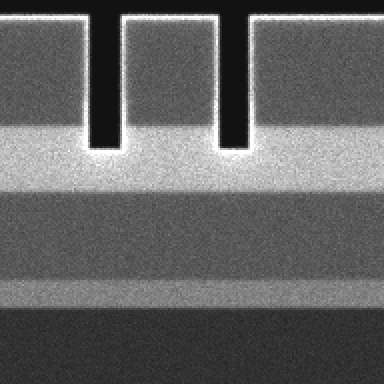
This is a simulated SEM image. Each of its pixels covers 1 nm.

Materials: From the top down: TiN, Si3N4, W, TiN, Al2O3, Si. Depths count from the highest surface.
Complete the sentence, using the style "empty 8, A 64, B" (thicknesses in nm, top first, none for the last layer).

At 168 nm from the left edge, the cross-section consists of TiN 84, Si3N4 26, W 66, TiN 88, Al2O3 28, Si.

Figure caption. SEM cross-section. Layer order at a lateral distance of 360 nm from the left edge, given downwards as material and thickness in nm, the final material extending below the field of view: TiN 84, Si3N4 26, W 66, TiN 88, Al2O3 28, Si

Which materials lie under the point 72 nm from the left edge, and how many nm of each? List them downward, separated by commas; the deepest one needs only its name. TiN 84, Si3N4 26, W 66, TiN 88, Al2O3 28, Si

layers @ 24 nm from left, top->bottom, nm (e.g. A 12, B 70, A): TiN 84, Si3N4 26, W 66, TiN 88, Al2O3 28, Si